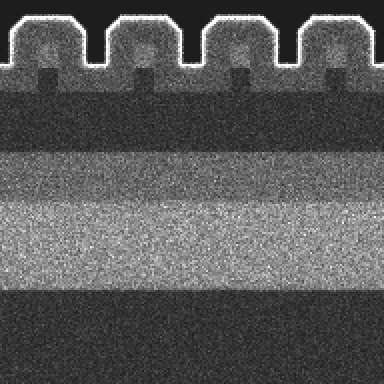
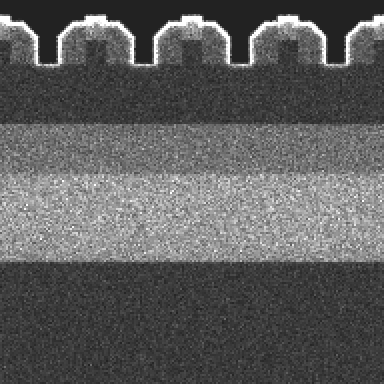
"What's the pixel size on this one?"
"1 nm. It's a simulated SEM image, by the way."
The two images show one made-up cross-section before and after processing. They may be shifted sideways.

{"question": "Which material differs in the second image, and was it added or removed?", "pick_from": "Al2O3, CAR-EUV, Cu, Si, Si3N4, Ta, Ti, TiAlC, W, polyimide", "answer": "Si3N4, removed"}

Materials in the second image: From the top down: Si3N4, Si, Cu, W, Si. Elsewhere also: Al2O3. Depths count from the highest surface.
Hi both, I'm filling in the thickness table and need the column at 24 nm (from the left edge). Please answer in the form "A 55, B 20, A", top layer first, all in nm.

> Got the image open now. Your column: empty 8, Si3N4 40, Si 60, Cu 50, W 88, Si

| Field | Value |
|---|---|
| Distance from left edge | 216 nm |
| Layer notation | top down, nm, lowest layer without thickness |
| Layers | empty 8, Si3N4 40, Si 60, Cu 50, W 88, Si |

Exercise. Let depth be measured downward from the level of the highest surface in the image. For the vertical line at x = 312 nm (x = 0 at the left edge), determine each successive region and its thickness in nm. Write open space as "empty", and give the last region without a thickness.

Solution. empty 8, Si3N4 40, Si 60, Cu 50, W 88, Si